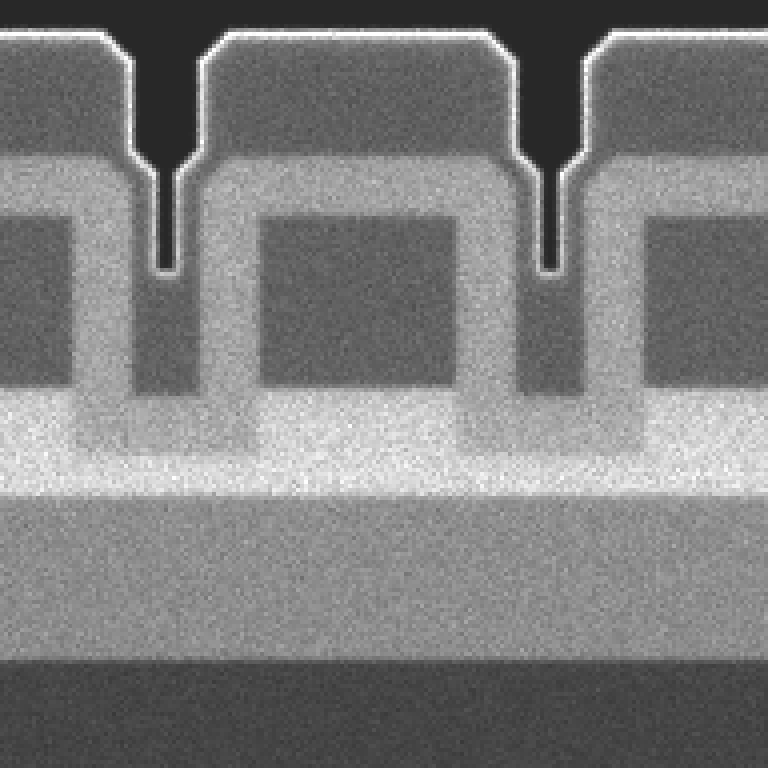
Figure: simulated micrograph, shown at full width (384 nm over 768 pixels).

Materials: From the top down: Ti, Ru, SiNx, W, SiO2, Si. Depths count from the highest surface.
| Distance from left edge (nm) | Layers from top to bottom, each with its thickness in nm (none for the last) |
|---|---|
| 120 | Ti 62, Ru 150, W 20, SiO2 82, Si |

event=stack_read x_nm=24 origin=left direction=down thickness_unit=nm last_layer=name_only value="Ti 62, Ru 30, SiNx 86, W 54, SiO2 82, Si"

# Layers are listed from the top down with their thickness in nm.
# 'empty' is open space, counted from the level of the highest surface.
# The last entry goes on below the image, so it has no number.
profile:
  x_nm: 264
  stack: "empty 66, Ti 116, Ru 30, W 20, SiO2 82, Si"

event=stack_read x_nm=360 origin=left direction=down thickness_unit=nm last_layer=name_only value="Ti 62, Ru 30, SiNx 86, W 54, SiO2 82, Si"